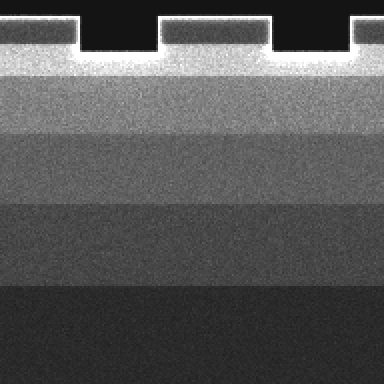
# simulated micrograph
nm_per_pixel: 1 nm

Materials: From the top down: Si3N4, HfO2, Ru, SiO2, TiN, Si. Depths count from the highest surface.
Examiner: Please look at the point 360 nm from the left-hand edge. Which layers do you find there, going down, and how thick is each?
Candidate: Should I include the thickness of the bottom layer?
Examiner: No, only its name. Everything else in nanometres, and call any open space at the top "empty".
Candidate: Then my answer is Si3N4 28, HfO2 32, Ru 58, SiO2 70, TiN 82, Si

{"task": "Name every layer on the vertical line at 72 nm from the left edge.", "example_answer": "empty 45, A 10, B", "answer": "Si3N4 28, HfO2 32, Ru 58, SiO2 70, TiN 82, Si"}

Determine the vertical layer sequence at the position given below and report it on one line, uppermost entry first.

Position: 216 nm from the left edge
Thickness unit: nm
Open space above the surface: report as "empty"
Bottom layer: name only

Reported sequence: Si3N4 28, HfO2 32, Ru 58, SiO2 70, TiN 82, Si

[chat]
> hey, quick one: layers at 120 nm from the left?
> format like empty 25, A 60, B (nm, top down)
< empty 36, HfO2 24, Ru 58, SiO2 70, TiN 82, Si